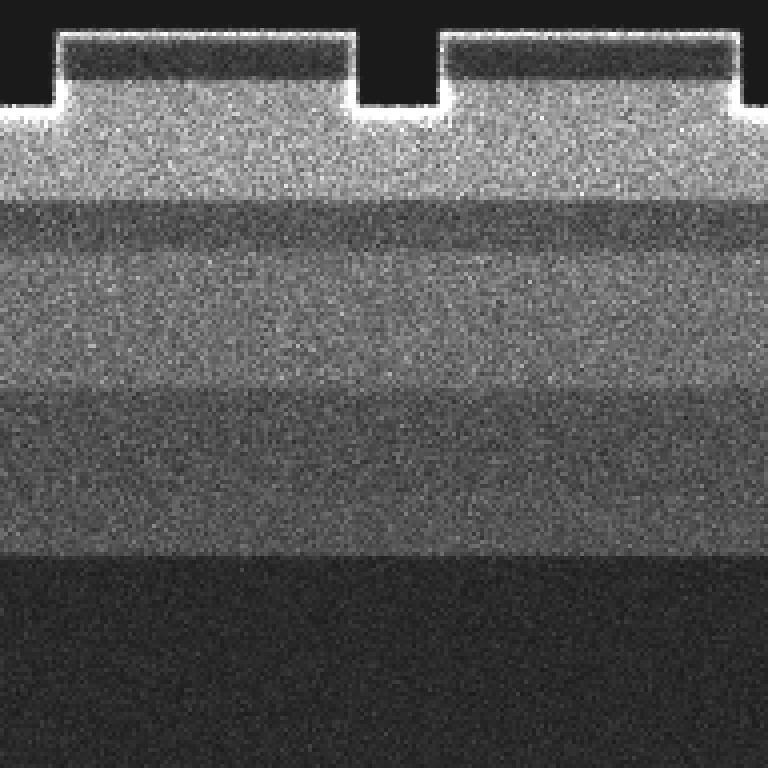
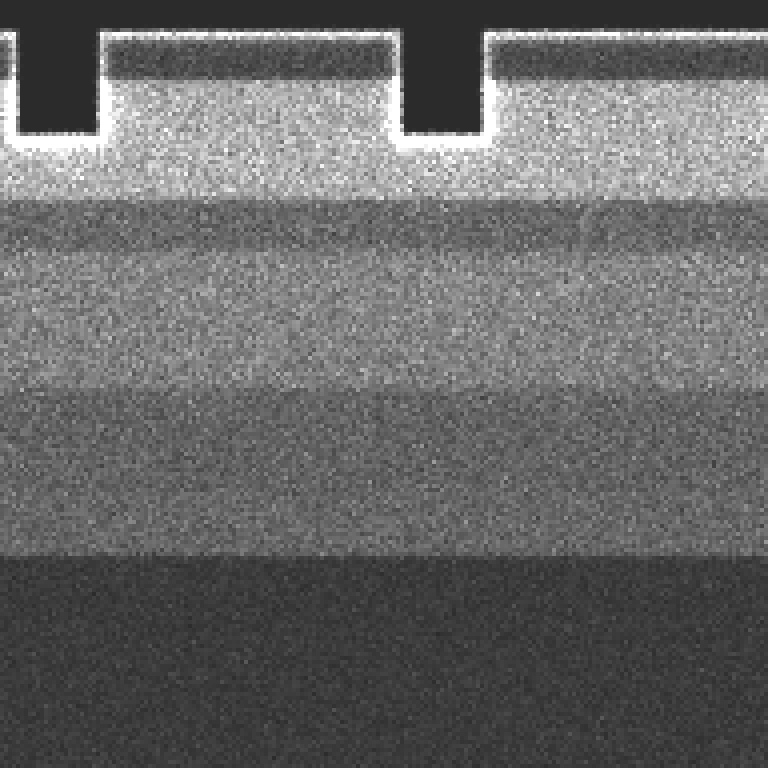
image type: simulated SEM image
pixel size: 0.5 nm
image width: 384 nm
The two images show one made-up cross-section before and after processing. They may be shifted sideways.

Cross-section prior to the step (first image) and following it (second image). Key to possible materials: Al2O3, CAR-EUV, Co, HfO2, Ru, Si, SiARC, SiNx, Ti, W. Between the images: HfO2 was removed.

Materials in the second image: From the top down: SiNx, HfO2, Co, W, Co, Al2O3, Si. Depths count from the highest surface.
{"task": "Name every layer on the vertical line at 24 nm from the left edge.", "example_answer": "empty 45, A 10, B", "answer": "empty 52, HfO2 32, Co 26, W 68, Co 52, Al2O3 32, Si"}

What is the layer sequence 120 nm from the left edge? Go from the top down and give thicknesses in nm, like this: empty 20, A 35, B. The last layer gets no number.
SiNx 24, HfO2 60, Co 26, W 68, Co 52, Al2O3 32, Si